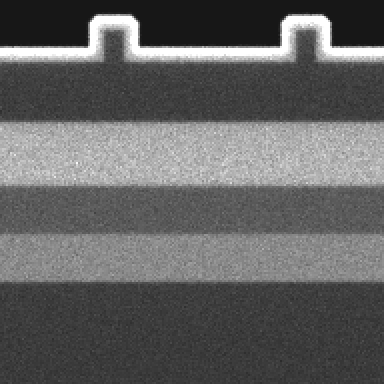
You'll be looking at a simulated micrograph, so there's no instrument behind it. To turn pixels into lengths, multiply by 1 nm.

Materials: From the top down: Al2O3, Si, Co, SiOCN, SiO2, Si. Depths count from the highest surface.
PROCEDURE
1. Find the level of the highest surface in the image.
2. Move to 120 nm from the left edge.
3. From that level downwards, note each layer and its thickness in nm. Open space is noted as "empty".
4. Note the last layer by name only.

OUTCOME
Al2O3 14, Si 92, Co 64, SiOCN 48, SiO2 48, Si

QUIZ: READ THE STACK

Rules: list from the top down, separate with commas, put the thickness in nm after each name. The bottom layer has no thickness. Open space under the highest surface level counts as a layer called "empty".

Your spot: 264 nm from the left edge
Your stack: empty 32, Al2O3 14, Si 60, Co 64, SiOCN 48, SiO2 48, Si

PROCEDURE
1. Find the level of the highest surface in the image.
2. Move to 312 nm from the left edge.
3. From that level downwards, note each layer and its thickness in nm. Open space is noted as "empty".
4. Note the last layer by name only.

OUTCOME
Al2O3 14, Si 92, Co 64, SiOCN 48, SiO2 48, Si